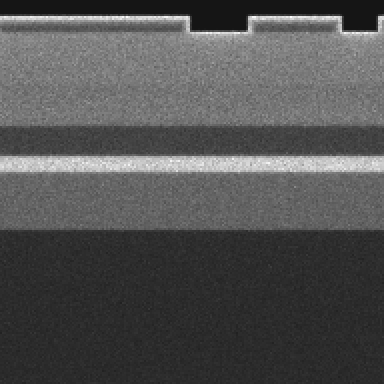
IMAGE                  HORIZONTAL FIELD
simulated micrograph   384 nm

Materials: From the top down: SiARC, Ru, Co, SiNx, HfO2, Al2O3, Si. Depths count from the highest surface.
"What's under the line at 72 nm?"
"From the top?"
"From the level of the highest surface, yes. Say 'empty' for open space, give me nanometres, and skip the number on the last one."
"SiARC 16, Ru 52, Co 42, SiNx 30, HfO2 16, Al2O3 58, Si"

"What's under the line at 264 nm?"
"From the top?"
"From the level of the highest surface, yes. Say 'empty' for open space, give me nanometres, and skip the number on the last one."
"SiARC 16, Ru 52, Co 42, SiNx 30, HfO2 16, Al2O3 58, Si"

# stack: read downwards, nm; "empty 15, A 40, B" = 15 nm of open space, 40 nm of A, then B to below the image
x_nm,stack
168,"SiARC 16, Ru 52, Co 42, SiNx 30, HfO2 16, Al2O3 58, Si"